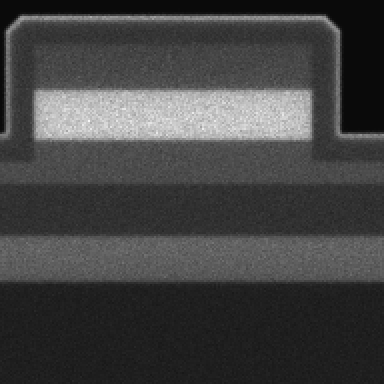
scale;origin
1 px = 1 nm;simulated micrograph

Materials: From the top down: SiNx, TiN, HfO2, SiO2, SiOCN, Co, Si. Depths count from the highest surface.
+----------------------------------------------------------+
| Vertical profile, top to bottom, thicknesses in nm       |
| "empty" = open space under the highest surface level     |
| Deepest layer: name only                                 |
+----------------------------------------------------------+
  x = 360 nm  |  empty 118, SiNx 28, SiO2 22, SiOCN 52, Co 46, Si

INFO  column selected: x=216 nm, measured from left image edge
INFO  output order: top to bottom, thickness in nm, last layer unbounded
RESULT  SiNx 28, TiN 46, HfO2 50, SiO2 44, SiOCN 52, Co 46, Si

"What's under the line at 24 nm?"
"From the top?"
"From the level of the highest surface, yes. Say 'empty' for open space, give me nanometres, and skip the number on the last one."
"SiNx 146, SiO2 22, SiOCN 52, Co 46, Si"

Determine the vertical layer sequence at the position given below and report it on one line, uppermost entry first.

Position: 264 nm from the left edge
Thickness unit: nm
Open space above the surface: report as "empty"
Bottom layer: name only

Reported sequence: SiNx 28, TiN 46, HfO2 50, SiO2 44, SiOCN 52, Co 46, Si